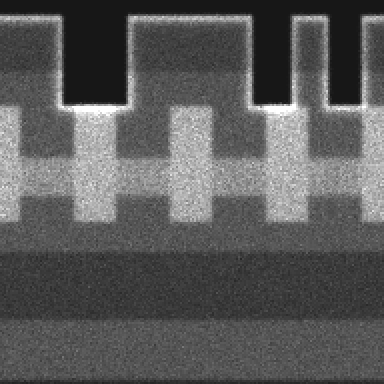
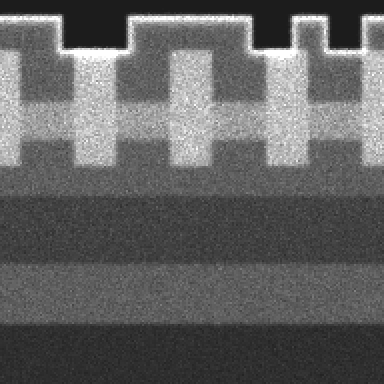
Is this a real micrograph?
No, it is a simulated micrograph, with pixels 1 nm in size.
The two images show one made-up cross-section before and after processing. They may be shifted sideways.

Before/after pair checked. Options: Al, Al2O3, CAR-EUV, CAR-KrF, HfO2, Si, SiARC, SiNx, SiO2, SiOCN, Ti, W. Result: removed SiARC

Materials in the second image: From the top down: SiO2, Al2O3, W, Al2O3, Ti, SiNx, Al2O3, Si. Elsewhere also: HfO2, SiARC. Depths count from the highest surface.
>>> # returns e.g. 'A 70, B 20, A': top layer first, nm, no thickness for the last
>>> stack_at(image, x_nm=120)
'empty 34, Al2O3 52, W 38, Al2O3 56, Ti 44, SiNx 24, Al2O3 60, Si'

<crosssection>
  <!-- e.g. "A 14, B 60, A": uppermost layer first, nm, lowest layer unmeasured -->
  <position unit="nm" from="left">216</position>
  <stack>SiO2 34, Al2O3 52, W 38, Al2O3 56, Ti 44, SiNx 24, Al2O3 60, Si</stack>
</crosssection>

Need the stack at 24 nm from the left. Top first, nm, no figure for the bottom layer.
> SiO2 34, Al2O3 52, W 38, Al2O3 56, Ti 44, SiNx 24, Al2O3 60, Si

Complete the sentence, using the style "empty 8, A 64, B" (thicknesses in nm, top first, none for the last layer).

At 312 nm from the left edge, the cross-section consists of SiO2 34, Al2O3 52, W 38, Al2O3 56, Ti 44, SiNx 24, Al2O3 60, Si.